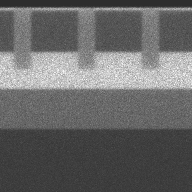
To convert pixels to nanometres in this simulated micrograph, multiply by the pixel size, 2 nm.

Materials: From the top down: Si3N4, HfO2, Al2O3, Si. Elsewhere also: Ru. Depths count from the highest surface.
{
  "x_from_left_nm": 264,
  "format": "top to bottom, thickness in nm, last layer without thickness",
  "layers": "Si3N4 88, HfO2 74, Al2O3 80, Si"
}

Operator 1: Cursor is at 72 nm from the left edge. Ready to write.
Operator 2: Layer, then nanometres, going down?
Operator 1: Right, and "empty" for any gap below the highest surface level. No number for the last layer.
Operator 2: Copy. Si3N4 88, HfO2 74, Al2O3 80, Si